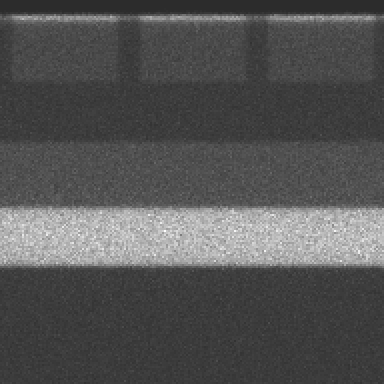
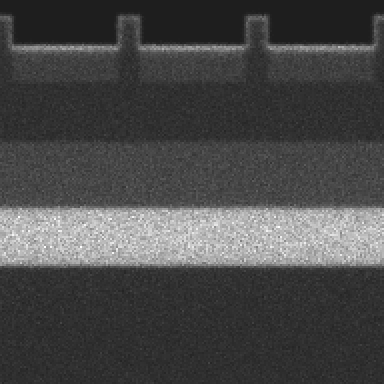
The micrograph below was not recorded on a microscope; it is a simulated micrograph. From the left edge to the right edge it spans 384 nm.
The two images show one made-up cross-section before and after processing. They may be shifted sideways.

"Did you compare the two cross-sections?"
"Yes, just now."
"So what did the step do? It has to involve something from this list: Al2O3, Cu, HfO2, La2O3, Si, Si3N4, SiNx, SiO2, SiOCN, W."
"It removed SiNx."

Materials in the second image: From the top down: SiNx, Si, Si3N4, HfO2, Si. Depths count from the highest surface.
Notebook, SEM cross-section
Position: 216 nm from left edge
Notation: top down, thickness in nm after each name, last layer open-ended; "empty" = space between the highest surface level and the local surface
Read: empty 30, SiNx 36, Si 60, Si3N4 66, HfO2 58, Si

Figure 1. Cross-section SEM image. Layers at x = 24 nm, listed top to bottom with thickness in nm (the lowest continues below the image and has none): empty 30, SiNx 36, Si 60, Si3N4 66, HfO2 58, Si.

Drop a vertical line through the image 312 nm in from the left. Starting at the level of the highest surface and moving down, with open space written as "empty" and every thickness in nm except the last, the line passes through empty 30, SiNx 36, Si 60, Si3N4 66, HfO2 58, Si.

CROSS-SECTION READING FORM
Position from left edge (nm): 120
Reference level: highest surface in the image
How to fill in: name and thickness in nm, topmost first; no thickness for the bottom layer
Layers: Si 126, Si3N4 66, HfO2 58, Si